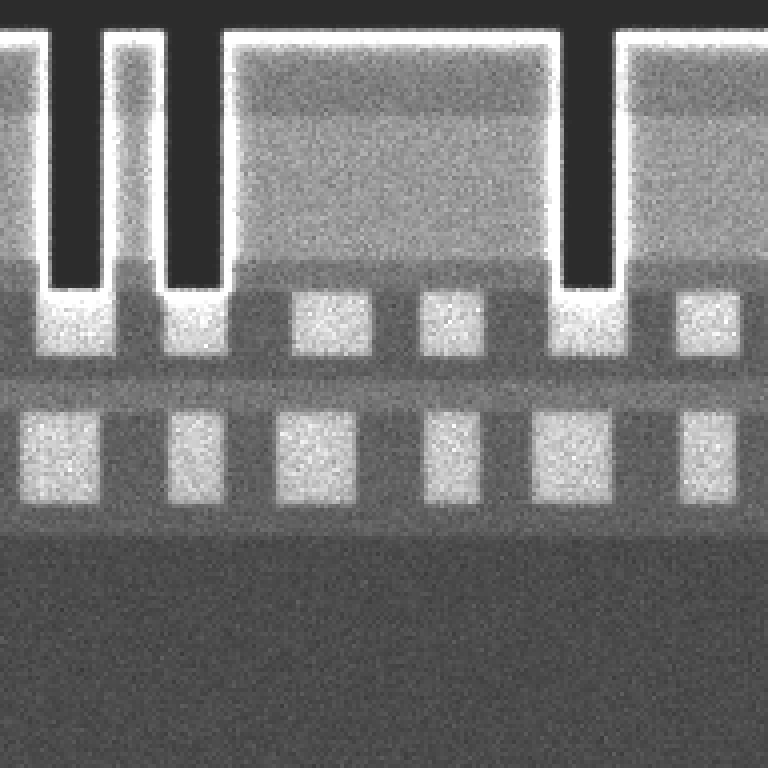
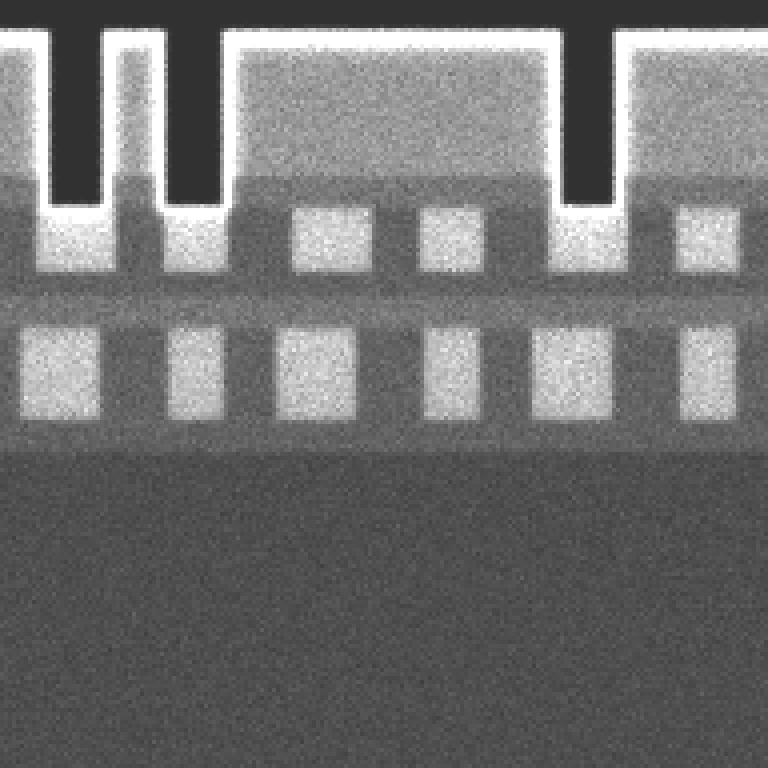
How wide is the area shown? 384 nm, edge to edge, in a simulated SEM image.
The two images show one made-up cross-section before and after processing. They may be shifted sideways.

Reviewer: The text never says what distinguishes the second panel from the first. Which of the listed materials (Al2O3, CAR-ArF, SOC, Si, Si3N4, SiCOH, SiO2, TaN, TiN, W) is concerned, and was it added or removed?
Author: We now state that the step removed SOC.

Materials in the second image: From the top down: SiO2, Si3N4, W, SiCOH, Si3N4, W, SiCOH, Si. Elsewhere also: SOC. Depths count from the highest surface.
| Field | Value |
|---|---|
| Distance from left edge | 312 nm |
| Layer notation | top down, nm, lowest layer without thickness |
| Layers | SiO2 72, Si3N4 16, W 32, SiCOH 12, Si3N4 16, SiCOH 62, Si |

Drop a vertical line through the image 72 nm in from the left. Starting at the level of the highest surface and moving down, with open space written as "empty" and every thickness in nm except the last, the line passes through SiO2 72, Si3N4 16, SiCOH 44, Si3N4 16, SiCOH 62, Si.